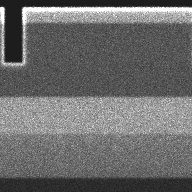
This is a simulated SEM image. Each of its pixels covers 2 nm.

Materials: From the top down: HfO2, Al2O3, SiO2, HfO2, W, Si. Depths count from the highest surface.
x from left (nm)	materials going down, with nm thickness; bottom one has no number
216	HfO2 30, Al2O3 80, SiO2 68, HfO2 74, W 88, Si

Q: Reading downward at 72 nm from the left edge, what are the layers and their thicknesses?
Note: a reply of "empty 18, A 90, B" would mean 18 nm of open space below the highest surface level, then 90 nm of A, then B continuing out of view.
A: HfO2 30, Al2O3 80, SiO2 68, HfO2 74, W 88, Si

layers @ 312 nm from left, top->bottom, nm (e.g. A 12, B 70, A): HfO2 30, Al2O3 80, SiO2 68, HfO2 74, W 88, Si